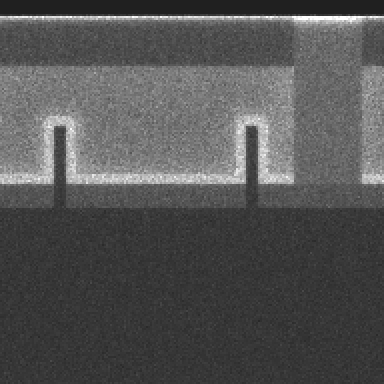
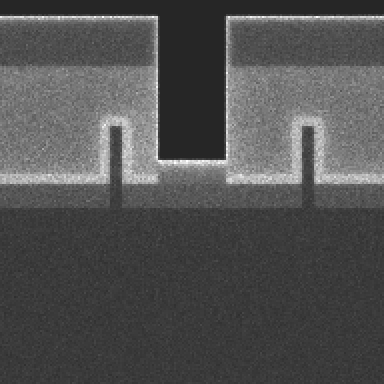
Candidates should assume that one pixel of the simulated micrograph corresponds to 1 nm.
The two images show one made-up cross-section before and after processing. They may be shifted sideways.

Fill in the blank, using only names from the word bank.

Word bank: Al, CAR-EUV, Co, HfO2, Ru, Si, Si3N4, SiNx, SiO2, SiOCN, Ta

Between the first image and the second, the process removed SiO2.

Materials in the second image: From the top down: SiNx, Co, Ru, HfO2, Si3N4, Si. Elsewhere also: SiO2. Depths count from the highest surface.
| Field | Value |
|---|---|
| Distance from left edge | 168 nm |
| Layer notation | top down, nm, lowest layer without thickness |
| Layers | empty 144, SiO2 24, Si3N4 24, Si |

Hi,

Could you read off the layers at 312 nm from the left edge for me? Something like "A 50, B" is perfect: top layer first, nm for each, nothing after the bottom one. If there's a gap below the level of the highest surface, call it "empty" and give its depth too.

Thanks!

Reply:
SiNx 50, Co 40, Ru 10, HfO2 10, Si